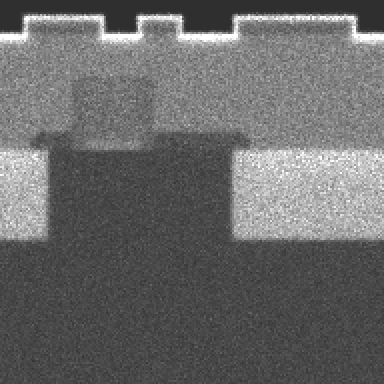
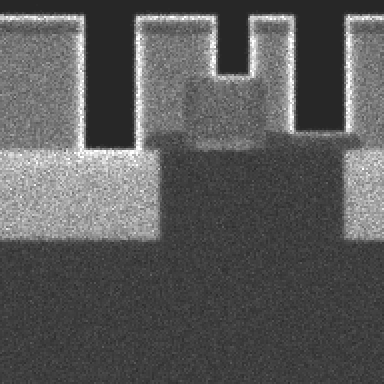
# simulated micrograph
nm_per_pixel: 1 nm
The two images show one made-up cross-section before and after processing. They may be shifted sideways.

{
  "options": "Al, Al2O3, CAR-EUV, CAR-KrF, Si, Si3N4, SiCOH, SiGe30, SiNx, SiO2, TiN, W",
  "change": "removed",
  "material": "SiO2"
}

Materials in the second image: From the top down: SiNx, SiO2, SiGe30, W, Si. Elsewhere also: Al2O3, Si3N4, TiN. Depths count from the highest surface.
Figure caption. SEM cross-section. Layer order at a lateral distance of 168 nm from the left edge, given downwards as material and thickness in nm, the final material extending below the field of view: SiNx 18, SiO2 98, SiGe30 18, Si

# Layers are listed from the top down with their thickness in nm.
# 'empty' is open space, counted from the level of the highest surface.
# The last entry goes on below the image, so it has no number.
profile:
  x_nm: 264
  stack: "SiNx 18, SiO2 48, Si3N4 68, Si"